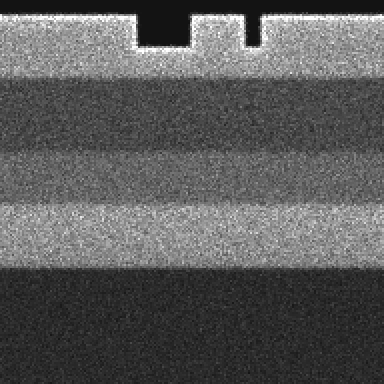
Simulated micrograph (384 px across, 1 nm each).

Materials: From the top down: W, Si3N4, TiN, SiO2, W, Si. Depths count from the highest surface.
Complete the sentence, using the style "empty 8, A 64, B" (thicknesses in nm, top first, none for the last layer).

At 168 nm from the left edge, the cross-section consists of empty 32, W 30, Si3N4 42, TiN 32, SiO2 52, W 64, Si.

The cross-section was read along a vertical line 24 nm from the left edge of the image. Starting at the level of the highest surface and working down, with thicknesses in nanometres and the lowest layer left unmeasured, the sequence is W 62, Si3N4 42, TiN 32, SiO2 52, W 64, Si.